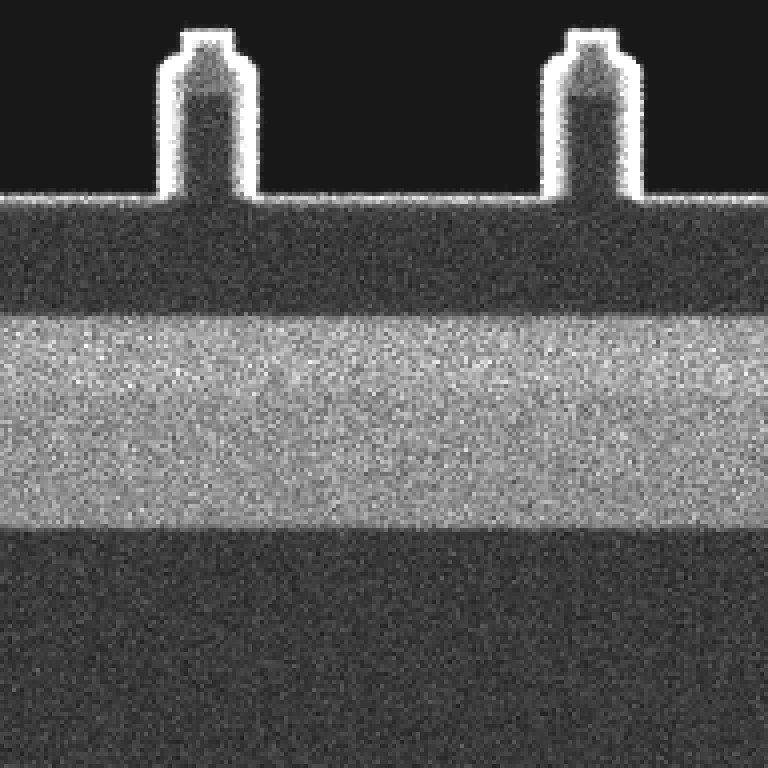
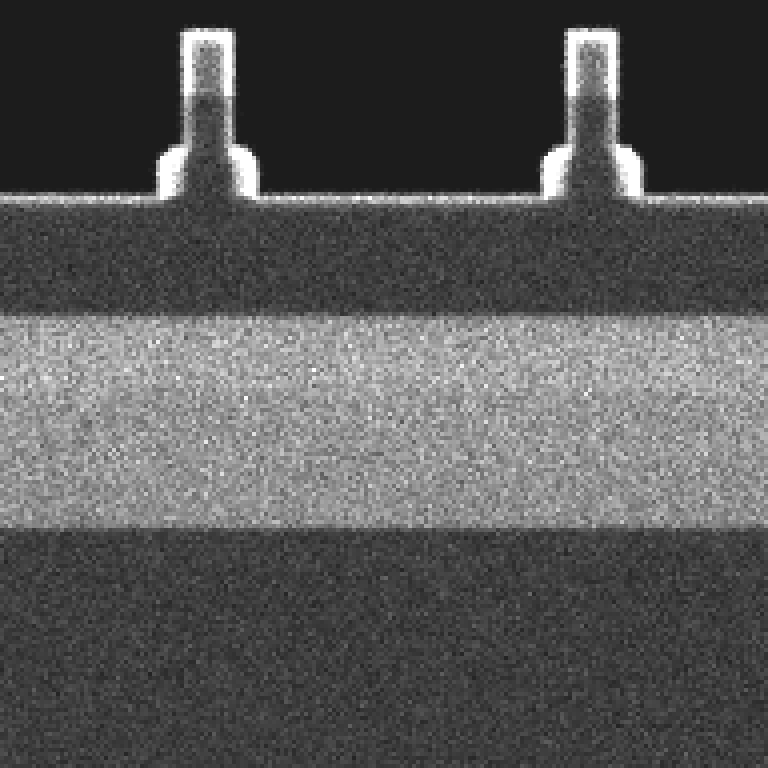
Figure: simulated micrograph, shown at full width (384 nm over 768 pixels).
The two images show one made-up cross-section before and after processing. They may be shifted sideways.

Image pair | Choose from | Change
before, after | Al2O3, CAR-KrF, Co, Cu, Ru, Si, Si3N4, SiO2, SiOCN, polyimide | Al2O3 (removed)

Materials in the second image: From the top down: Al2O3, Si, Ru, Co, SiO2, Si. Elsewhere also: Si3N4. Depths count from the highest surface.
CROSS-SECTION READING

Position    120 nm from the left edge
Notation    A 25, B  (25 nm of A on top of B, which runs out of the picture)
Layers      empty 58, Al2O3 24, Si 60, Ru 38, Co 42, SiO2 26, Si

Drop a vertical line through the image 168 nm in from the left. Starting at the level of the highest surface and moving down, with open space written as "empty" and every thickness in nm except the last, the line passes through empty 82, Si 60, Ru 38, Co 42, SiO2 26, Si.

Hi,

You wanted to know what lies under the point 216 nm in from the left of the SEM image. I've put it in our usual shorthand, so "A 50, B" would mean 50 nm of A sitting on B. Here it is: empty 82, Si 60, Ru 38, Co 42, SiO2 26, Si